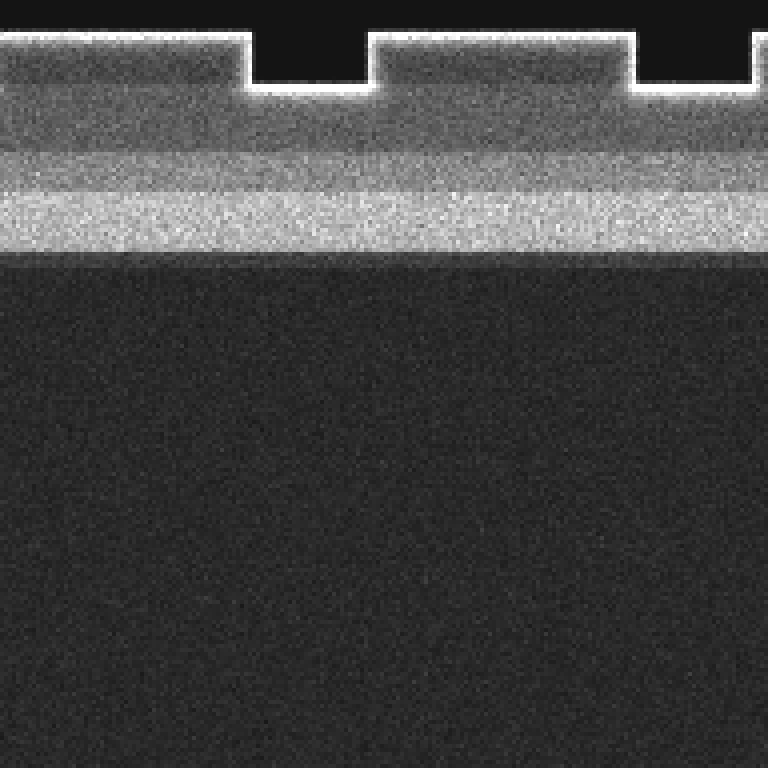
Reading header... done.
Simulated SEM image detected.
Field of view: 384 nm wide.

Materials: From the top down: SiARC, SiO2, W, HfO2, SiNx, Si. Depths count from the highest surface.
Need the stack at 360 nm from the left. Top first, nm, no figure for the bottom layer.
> empty 26, SiO2 34, W 20, HfO2 30, SiNx 8, Si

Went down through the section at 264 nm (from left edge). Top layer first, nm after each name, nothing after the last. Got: SiARC 26, SiO2 34, W 20, HfO2 30, SiNx 8, Si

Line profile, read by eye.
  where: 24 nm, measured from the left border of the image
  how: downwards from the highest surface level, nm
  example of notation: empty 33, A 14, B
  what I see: SiARC 26, SiO2 34, W 20, HfO2 30, SiNx 8, Si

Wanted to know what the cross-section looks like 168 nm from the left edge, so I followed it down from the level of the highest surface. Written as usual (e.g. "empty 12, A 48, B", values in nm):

empty 26, SiO2 34, W 20, HfO2 30, SiNx 8, Si